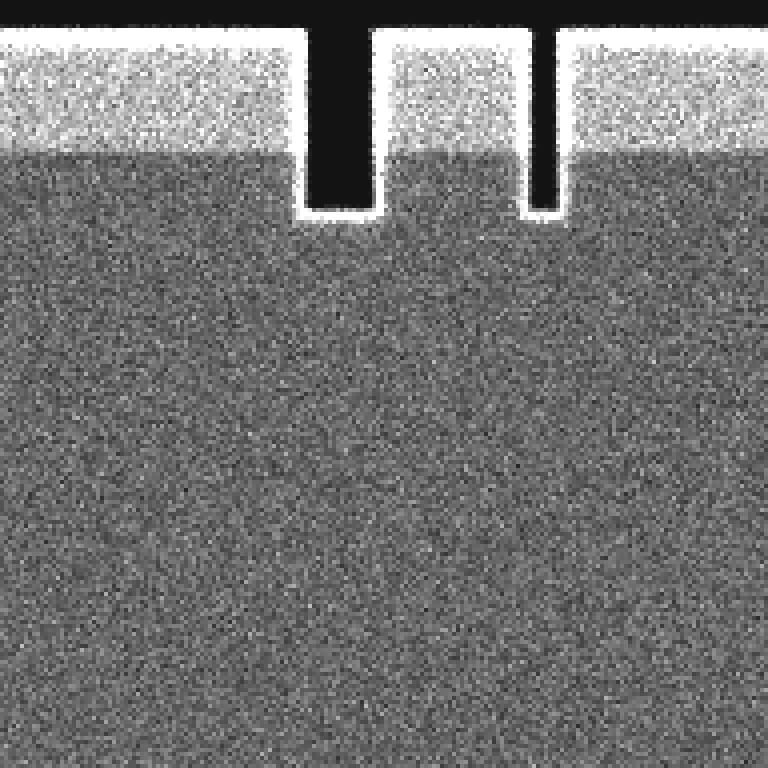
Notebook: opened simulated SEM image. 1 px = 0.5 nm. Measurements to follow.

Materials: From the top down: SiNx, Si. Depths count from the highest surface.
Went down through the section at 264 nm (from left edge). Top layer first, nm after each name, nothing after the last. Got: empty 90, Si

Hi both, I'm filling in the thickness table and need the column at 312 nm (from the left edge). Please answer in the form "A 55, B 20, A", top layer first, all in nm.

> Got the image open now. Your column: SiNx 60, Si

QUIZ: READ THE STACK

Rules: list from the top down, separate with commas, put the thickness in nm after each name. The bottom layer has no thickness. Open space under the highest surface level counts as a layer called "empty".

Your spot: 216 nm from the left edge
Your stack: SiNx 60, Si